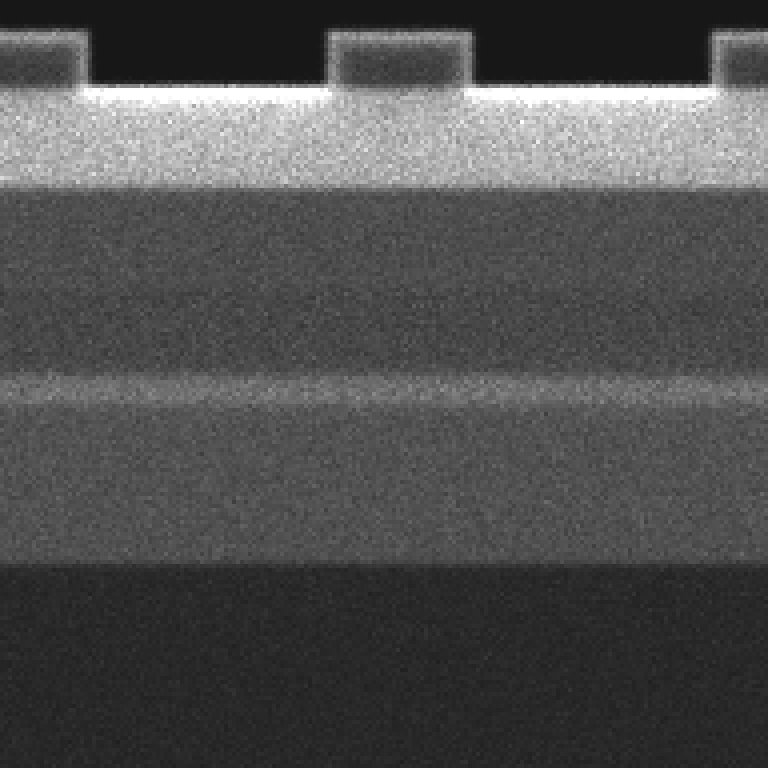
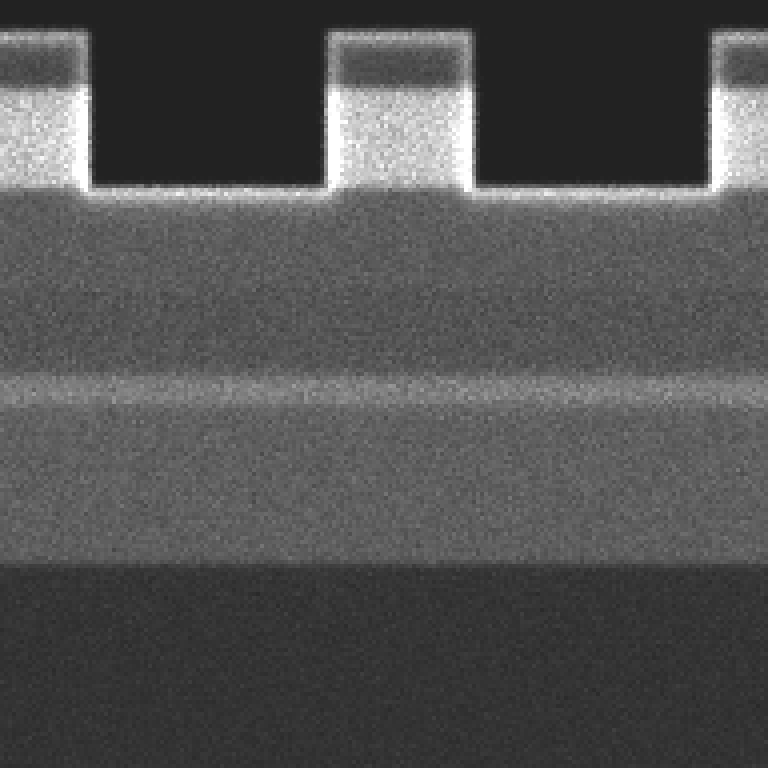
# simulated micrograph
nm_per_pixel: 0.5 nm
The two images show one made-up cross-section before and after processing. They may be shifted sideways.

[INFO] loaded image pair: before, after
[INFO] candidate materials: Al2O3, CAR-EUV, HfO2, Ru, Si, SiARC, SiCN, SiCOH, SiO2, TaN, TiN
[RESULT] removed HfO2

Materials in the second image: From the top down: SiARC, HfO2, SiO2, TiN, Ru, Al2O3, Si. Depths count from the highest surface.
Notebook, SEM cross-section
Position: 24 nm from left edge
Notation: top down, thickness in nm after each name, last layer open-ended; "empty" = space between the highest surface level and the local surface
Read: SiARC 28, HfO2 50, SiO2 50, TiN 44, Ru 14, Al2O3 80, Si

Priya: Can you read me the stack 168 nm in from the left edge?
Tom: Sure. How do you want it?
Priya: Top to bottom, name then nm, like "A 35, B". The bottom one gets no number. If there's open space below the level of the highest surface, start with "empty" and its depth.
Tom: SiARC 28, HfO2 50, SiO2 50, TiN 44, Ru 14, Al2O3 80, Si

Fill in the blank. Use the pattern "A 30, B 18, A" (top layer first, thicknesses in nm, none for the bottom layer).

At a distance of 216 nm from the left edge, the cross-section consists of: SiARC 28, HfO2 50, SiO2 50, TiN 44, Ru 14, Al2O3 80, Si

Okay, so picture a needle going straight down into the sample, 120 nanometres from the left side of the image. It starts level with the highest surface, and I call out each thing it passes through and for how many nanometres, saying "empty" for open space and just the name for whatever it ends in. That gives empty 78, SiO2 50, TiN 44, Ru 14, Al2O3 80, Si